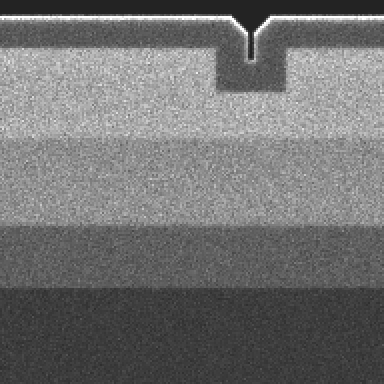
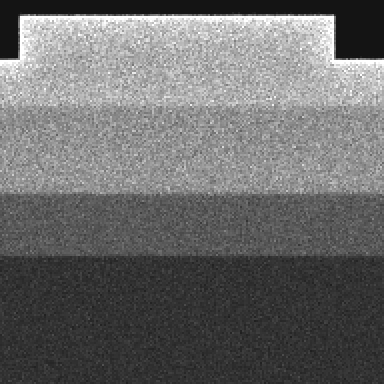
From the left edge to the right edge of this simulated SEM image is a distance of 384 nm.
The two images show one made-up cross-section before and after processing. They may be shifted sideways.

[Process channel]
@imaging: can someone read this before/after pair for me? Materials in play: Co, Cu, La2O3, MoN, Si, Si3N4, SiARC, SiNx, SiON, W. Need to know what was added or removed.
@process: SiNx removed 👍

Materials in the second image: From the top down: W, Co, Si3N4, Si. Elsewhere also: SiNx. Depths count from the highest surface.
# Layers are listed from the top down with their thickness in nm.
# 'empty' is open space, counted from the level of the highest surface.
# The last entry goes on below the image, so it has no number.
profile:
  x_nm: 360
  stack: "empty 44, W 46, Co 88, Si3N4 62, Si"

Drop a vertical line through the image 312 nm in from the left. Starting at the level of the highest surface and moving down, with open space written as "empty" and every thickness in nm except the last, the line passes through W 90, Co 88, Si3N4 62, Si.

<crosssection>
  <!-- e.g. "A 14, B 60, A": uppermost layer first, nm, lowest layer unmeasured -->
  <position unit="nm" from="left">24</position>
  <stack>W 90, Co 88, Si3N4 62, Si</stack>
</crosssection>